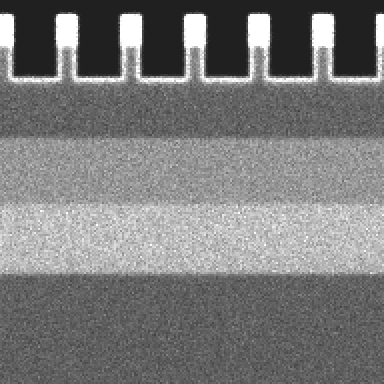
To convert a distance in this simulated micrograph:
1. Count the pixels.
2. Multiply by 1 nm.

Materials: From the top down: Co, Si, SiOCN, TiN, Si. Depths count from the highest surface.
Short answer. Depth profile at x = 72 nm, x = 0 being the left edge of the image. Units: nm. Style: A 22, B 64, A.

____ Co 30, Si 92, SiOCN 66, TiN 70, Si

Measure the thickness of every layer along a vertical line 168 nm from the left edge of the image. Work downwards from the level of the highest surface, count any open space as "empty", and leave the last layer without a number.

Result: empty 62, Si 60, SiOCN 66, TiN 70, Si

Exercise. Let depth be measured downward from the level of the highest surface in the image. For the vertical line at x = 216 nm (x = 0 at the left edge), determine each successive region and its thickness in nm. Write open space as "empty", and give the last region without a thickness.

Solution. empty 62, Si 60, SiOCN 66, TiN 70, Si